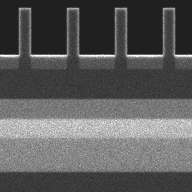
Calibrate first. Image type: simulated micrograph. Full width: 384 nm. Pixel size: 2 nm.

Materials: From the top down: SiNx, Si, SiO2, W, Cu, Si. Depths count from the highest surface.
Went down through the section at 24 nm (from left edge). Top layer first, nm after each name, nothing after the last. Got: empty 94, SiNx 28, Si 60, SiO2 40, W 38, Cu 68, Si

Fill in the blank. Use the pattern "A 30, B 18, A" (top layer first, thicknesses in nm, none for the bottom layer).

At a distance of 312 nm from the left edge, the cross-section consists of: empty 94, SiNx 28, Si 60, SiO2 40, W 38, Cu 68, Si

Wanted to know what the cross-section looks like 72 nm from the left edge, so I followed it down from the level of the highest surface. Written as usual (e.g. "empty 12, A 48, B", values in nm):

empty 94, SiNx 28, Si 60, SiO2 40, W 38, Cu 68, Si